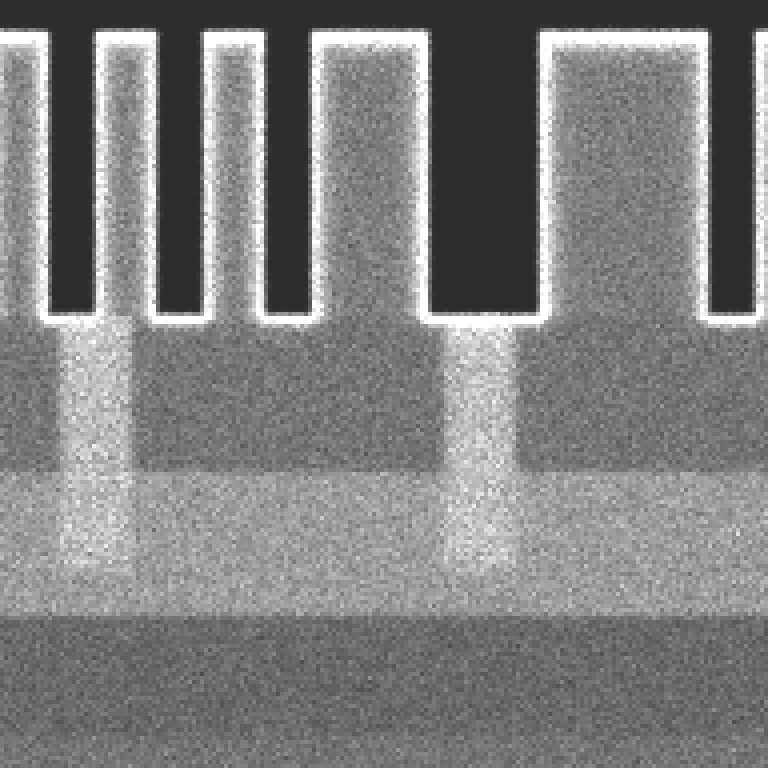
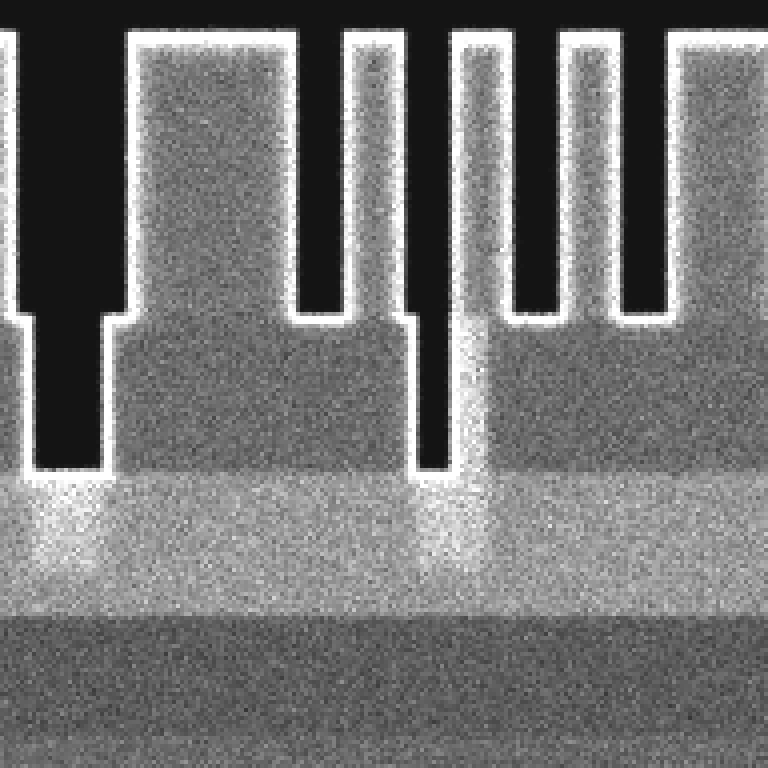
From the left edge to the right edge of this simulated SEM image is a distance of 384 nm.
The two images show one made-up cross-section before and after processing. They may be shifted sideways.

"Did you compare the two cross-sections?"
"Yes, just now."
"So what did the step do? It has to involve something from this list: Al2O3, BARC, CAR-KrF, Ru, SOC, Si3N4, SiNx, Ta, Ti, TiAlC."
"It removed Ru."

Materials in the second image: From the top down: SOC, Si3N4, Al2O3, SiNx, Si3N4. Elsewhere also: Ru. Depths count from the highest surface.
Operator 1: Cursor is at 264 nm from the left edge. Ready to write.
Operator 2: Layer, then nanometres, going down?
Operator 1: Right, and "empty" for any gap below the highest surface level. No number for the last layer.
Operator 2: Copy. empty 142, Si3N4 78, Al2O3 72, SiNx 60, Si3N4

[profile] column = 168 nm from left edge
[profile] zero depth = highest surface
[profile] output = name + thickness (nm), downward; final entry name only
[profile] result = empty 142, Si3N4 78, Al2O3 72, SiNx 60, Si3N4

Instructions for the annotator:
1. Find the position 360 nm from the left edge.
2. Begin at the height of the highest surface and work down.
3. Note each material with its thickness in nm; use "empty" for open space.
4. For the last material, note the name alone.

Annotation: SOC 142, Si3N4 78, Al2O3 72, SiNx 60, Si3N4